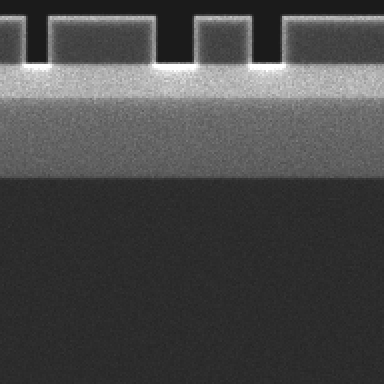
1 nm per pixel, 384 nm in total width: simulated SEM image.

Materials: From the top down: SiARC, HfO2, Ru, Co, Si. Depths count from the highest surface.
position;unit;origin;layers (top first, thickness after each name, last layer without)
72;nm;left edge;SiARC 48, HfO2 34, Ru 8, Co 72, Si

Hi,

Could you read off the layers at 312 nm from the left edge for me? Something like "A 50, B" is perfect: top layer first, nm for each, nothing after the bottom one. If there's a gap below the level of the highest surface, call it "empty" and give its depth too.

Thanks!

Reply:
SiARC 48, HfO2 34, Ru 8, Co 72, Si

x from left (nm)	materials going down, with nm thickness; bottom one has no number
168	empty 48, HfO2 34, Ru 8, Co 72, Si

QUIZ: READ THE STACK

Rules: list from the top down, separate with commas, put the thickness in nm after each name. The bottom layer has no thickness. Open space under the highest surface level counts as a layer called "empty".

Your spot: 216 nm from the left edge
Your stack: SiARC 48, HfO2 34, Ru 8, Co 72, Si